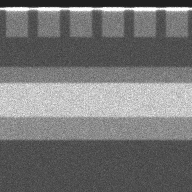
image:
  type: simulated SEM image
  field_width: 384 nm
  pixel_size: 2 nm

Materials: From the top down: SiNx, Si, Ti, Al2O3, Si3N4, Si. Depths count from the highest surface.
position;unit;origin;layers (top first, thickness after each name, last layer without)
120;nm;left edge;Si 118, Ti 32, Al2O3 68, Si3N4 46, Si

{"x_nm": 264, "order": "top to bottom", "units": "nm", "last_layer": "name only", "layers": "Si 118, Ti 32, Al2O3 68, Si3N4 46, Si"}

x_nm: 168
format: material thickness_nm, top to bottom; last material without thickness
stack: SiNx 58, Si 60, Ti 32, Al2O3 68, Si3N4 46, Si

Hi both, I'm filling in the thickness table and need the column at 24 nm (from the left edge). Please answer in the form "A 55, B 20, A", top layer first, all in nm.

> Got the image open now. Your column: SiNx 58, Si 60, Ti 32, Al2O3 68, Si3N4 46, Si